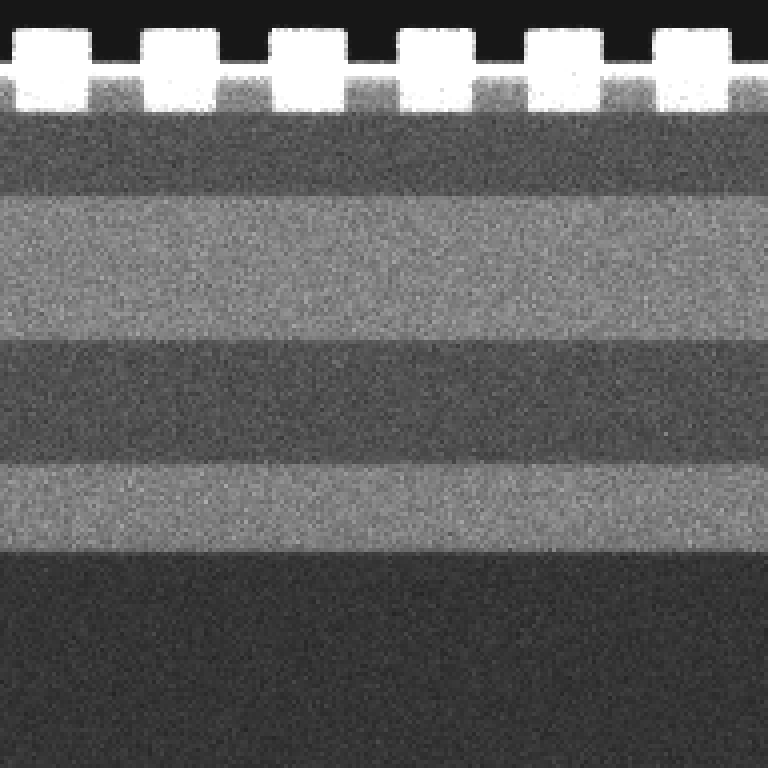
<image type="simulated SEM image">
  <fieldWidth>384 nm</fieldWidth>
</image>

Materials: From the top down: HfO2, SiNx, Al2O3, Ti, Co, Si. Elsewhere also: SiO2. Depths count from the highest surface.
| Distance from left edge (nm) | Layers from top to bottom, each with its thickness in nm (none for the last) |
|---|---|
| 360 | HfO2 40, SiNx 42, Al2O3 72, Ti 62, Co 44, Si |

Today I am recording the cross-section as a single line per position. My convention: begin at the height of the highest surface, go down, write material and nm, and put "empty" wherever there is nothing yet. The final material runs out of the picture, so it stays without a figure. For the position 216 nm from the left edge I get HfO2 40, SiNx 42, Al2O3 72, Ti 62, Co 44, Si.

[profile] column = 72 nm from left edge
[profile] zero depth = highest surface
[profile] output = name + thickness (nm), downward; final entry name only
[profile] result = HfO2 40, SiNx 42, Al2O3 72, Ti 62, Co 44, Si